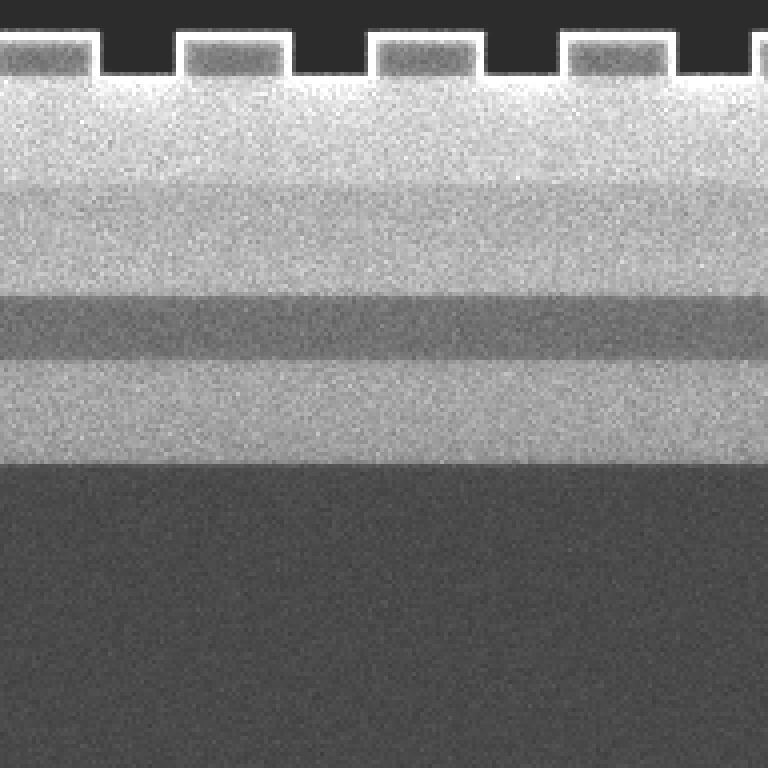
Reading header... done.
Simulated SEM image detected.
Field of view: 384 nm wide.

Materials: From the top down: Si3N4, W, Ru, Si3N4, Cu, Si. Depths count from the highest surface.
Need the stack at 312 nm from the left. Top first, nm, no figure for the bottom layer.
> Si3N4 22, W 54, Ru 56, Si3N4 32, Cu 52, Si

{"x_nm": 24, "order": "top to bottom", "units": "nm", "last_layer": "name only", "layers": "Si3N4 22, W 54, Ru 56, Si3N4 32, Cu 52, Si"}